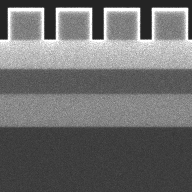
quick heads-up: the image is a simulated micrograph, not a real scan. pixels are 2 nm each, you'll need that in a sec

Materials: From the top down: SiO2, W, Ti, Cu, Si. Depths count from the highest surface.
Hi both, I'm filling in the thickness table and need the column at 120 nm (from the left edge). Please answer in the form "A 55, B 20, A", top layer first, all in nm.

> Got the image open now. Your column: SiO2 64, W 58, Ti 50, Cu 66, Si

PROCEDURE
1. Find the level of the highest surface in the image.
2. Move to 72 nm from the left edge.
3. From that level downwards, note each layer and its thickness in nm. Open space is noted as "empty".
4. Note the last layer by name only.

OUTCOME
SiO2 64, W 58, Ti 50, Cu 66, Si